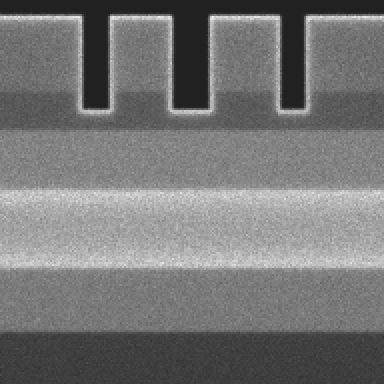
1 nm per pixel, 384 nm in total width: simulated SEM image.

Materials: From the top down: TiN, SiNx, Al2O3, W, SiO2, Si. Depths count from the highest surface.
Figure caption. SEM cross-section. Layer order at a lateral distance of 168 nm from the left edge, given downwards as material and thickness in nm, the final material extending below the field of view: TiN 76, SiNx 38, Al2O3 60, W 78, SiO2 64, Si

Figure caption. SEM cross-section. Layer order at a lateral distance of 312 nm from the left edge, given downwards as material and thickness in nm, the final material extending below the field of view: TiN 76, SiNx 38, Al2O3 60, W 78, SiO2 64, Si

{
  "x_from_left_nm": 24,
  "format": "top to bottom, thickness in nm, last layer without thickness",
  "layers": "TiN 76, SiNx 38, Al2O3 60, W 78, SiO2 64, Si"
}